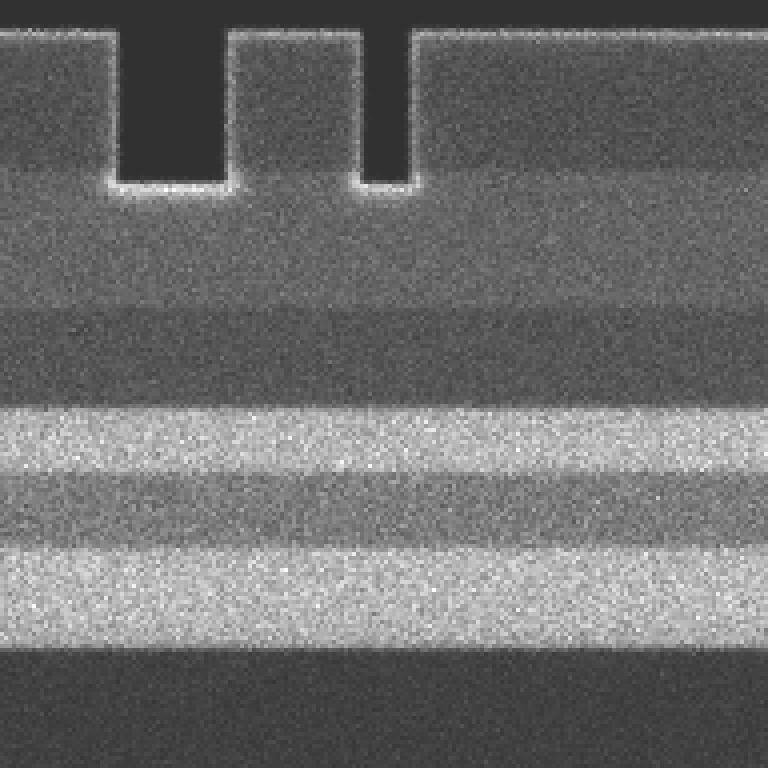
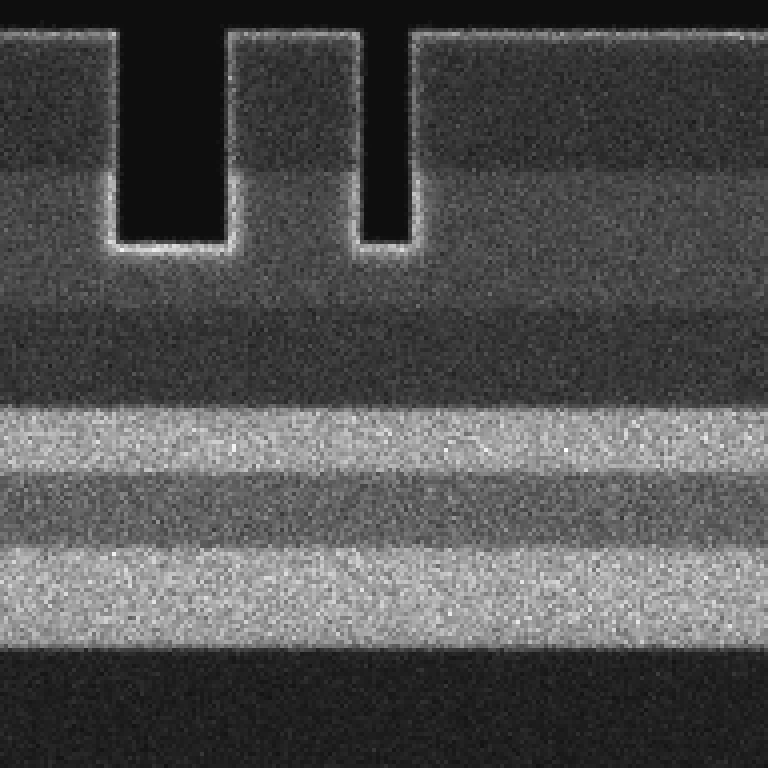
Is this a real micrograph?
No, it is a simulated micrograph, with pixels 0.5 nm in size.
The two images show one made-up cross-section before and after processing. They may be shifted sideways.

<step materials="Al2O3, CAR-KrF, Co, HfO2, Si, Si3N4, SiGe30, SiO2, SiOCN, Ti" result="removed SiO2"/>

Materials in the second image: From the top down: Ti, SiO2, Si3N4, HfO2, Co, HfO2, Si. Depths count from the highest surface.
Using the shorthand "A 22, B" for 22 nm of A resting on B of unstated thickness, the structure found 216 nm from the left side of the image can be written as Ti 70, SiO2 68, Si3N4 50, HfO2 32, Co 38, HfO2 50, Si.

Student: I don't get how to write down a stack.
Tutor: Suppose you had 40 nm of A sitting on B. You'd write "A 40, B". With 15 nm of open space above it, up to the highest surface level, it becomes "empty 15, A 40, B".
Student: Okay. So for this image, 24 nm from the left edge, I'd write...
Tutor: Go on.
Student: Ti 70, SiO2 68, Si3N4 50, HfO2 32, Co 38, HfO2 50, Si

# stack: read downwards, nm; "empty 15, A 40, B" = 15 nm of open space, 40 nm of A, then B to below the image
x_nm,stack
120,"Ti 70, SiO2 68, Si3N4 50, HfO2 32, Co 38, HfO2 50, Si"